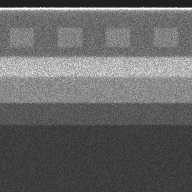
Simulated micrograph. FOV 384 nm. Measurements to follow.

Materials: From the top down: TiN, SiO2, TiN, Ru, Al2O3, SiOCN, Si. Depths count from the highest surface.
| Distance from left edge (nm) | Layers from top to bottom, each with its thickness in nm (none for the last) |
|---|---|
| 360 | TiN 98, Ru 40, Al2O3 52, SiOCN 44, Si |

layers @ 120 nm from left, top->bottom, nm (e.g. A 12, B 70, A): TiN 40, SiO2 38, TiN 20, Ru 40, Al2O3 52, SiOCN 44, Si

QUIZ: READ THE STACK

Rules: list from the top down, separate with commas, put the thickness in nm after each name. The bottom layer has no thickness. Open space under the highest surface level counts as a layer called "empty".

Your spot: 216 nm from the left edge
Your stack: TiN 40, SiO2 38, TiN 20, Ru 40, Al2O3 52, SiOCN 44, Si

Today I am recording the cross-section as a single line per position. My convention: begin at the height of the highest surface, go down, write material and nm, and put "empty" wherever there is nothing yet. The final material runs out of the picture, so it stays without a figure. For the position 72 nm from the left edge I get TiN 98, Ru 40, Al2O3 52, SiOCN 44, Si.